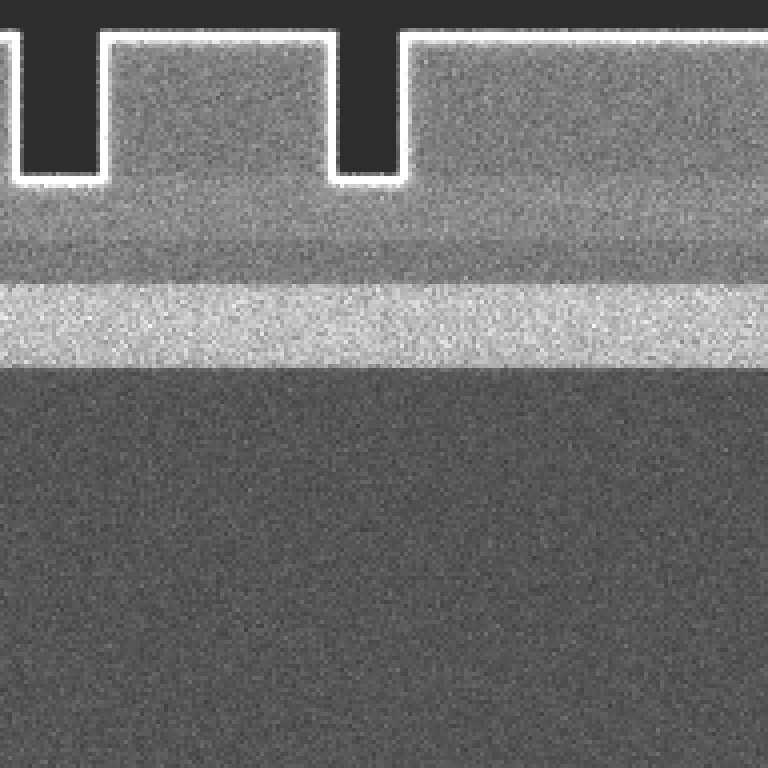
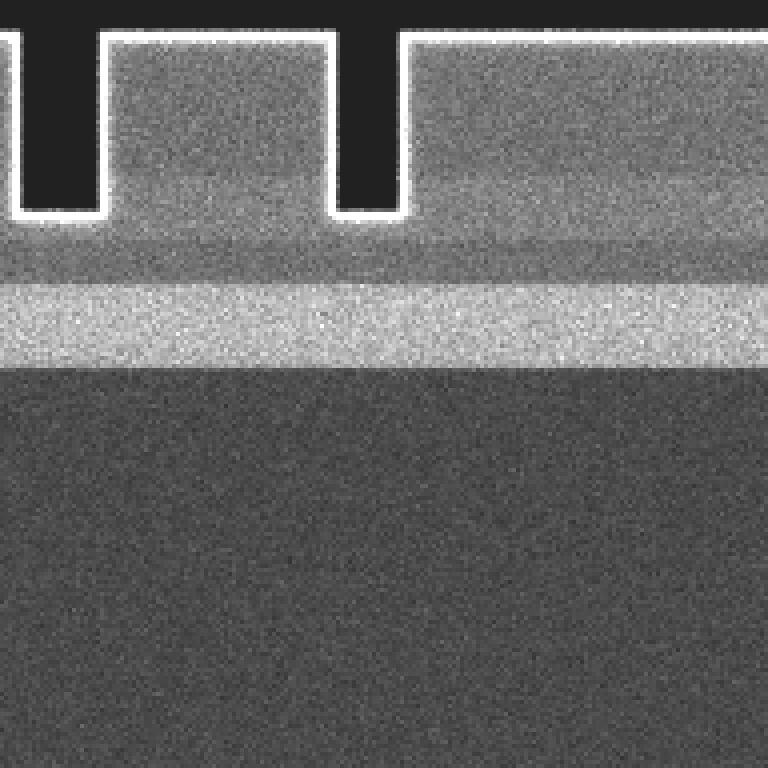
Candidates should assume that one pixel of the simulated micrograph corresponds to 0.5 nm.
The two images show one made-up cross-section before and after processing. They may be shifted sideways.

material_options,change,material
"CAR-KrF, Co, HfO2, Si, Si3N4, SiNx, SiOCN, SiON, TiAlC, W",removed,Si3N4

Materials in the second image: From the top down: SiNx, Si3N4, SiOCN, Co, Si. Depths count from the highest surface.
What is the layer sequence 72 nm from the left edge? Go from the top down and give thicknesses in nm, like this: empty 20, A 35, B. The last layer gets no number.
SiNx 72, Si3N4 32, SiOCN 22, Co 42, Si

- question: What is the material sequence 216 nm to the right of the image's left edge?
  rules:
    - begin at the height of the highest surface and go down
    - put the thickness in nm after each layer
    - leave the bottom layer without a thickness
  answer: SiNx 72, Si3N4 32, SiOCN 22, Co 42, Si